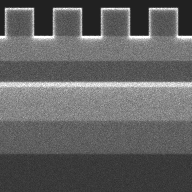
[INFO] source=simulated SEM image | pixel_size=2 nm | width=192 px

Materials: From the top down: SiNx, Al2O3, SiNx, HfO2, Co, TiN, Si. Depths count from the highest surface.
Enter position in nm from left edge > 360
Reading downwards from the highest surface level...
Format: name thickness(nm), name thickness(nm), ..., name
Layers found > empty 56, Al2O3 50, SiNx 42, HfO2 10, Co 68, TiN 66, Si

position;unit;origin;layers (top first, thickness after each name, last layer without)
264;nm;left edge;empty 56, Al2O3 50, SiNx 42, HfO2 10, Co 68, TiN 66, Si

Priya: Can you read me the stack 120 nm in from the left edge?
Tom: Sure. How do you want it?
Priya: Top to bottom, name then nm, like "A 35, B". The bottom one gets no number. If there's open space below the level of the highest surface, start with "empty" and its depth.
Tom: SiNx 56, Al2O3 50, SiNx 42, HfO2 10, Co 68, TiN 66, Si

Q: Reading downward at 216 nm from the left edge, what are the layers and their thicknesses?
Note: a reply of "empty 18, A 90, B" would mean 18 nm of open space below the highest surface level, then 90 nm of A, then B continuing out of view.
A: SiNx 56, Al2O3 50, SiNx 42, HfO2 10, Co 68, TiN 66, Si